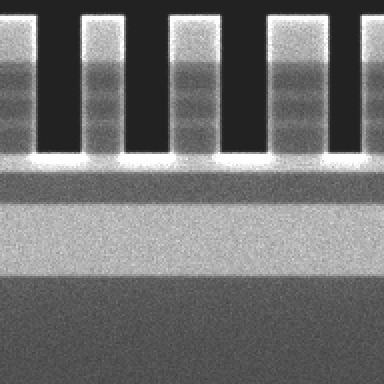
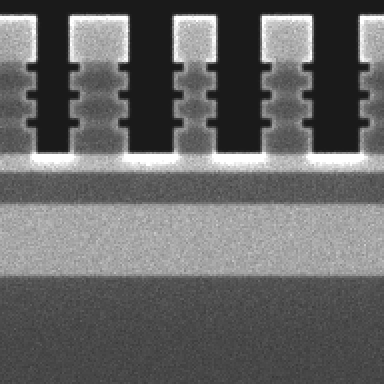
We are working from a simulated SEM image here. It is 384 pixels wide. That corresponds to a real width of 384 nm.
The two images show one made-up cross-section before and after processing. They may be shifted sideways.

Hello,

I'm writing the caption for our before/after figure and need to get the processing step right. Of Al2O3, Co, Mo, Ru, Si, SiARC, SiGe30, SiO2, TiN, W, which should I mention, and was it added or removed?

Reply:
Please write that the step removed SiGe30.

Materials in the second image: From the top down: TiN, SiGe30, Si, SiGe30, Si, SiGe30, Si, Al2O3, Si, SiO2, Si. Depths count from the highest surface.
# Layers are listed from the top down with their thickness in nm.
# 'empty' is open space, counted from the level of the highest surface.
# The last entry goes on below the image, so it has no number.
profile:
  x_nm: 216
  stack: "empty 138, Al2O3 18, Si 32, SiO2 72, Si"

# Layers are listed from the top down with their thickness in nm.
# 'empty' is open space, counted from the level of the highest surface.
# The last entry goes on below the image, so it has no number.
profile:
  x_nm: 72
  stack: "TiN 46, empty 10, Si 18, empty 10, Si 18, empty 10, Si 26, Al2O3 18, Si 32, SiO2 72, Si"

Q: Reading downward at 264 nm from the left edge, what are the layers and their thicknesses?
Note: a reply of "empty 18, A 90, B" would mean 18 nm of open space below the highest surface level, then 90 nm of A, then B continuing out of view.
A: TiN 46, empty 10, Si 18, empty 10, Si 18, empty 10, Si 26, Al2O3 18, Si 32, SiO2 72, Si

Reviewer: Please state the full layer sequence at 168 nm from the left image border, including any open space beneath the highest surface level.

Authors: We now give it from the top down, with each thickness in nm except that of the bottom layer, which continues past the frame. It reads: empty 138, Al2O3 18, Si 32, SiO2 72, Si